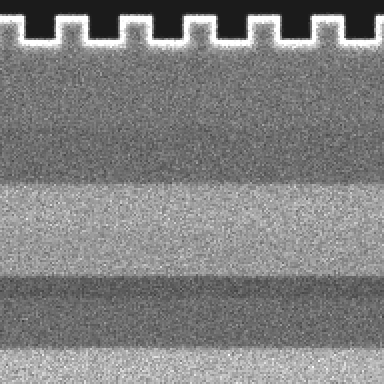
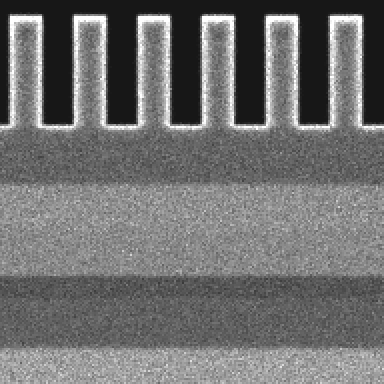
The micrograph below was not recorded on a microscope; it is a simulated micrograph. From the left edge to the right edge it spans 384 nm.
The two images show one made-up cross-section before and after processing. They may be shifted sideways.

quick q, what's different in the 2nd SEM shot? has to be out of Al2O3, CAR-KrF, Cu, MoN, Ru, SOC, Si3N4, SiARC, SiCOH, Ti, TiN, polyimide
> SOC removed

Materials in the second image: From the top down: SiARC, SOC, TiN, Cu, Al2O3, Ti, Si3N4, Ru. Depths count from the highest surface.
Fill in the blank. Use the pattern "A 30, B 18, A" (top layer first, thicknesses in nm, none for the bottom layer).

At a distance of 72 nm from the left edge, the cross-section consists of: empty 110, TiN 58, Cu 48, Al2O3 44, Ti 22, Si3N4 50, Ru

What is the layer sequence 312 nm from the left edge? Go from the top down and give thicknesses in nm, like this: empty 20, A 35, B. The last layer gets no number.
empty 110, TiN 58, Cu 48, Al2O3 44, Ti 22, Si3N4 50, Ru